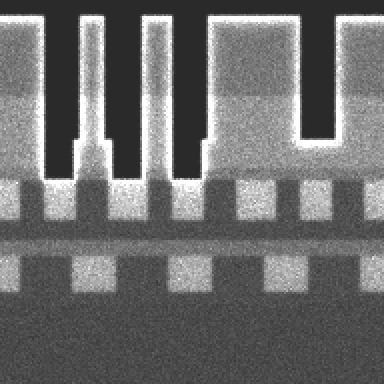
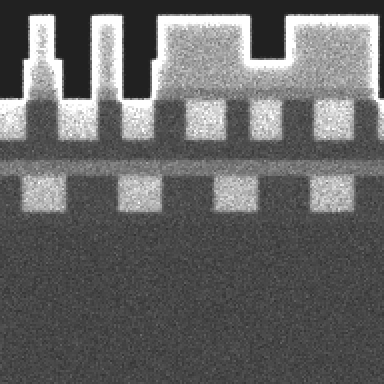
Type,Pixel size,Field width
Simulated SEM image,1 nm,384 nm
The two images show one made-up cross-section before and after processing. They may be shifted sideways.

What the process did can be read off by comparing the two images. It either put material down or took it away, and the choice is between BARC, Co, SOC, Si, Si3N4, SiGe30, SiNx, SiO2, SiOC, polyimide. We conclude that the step removed SOC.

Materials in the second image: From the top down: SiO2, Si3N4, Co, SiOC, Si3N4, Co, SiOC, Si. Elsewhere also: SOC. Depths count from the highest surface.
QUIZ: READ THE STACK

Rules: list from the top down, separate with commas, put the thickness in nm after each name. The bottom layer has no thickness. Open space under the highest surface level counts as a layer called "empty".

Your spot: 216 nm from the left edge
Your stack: SiO2 72, Si3N4 12, Co 40, SiOC 20, Si3N4 16, Co 36, SiOC 12, Si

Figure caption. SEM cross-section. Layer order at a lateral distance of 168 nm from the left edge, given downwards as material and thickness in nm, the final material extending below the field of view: SiO2 72, Si3N4 12, SiOC 60, Si3N4 16, SiOC 48, Si